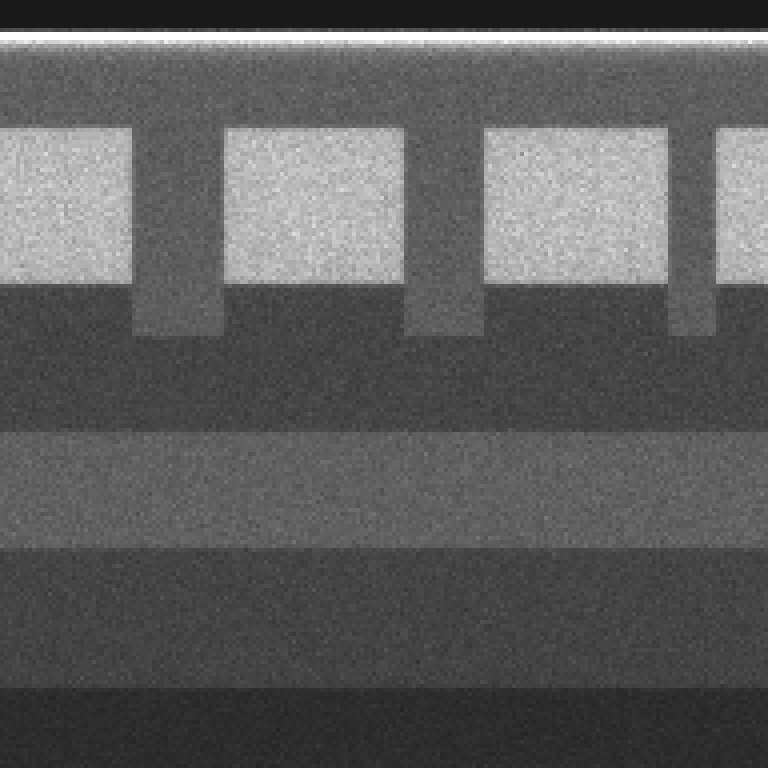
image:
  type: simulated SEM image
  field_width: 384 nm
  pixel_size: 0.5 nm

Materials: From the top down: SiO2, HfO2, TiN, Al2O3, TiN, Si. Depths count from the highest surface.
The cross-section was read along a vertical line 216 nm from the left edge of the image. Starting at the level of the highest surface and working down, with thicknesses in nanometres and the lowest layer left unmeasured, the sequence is SiO2 152, TiN 48, Al2O3 58, TiN 70, Si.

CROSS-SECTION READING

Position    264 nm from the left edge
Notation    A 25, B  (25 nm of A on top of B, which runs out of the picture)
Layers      SiO2 48, HfO2 78, TiN 74, Al2O3 58, TiN 70, Si